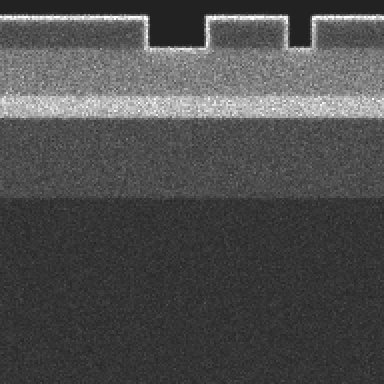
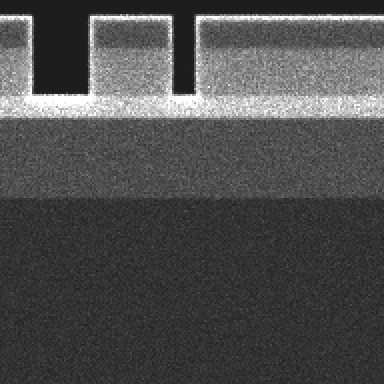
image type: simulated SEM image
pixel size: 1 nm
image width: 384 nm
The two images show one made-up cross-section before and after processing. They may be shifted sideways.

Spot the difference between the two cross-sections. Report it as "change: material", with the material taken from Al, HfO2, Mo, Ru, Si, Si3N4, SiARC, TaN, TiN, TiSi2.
removed: Ru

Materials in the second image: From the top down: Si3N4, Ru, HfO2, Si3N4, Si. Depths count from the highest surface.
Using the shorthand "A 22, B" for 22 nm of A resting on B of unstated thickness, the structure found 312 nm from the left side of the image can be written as Si3N4 32, Ru 48, HfO2 22, Si3N4 80, Si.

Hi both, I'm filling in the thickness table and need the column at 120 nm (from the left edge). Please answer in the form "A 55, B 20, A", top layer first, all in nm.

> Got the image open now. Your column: Si3N4 32, Ru 48, HfO2 22, Si3N4 80, Si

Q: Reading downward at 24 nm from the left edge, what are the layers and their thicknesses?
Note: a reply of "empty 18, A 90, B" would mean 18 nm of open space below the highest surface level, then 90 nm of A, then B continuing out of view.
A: Si3N4 32, Ru 48, HfO2 22, Si3N4 80, Si